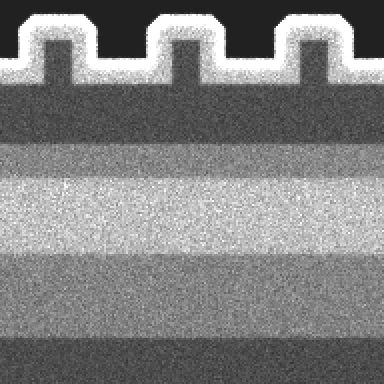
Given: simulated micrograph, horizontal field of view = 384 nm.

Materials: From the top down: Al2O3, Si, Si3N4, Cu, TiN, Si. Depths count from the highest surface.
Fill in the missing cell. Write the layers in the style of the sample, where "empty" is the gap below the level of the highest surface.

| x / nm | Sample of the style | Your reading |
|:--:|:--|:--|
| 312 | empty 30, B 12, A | Al2O3 24, Si 104, Si3N4 34, Cu 76, TiN 84, Si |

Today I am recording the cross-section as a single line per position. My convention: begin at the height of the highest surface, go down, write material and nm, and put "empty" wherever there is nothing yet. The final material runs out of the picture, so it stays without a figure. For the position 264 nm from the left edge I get empty 44, Al2O3 24, Si 60, Si3N4 34, Cu 76, TiN 84, Si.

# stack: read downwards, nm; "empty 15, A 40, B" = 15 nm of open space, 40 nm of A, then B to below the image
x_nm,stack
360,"empty 44, Al2O3 24, Si 60, Si3N4 34, Cu 76, TiN 84, Si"